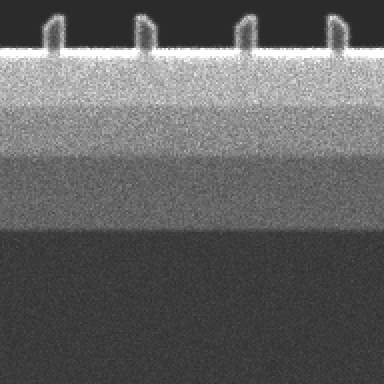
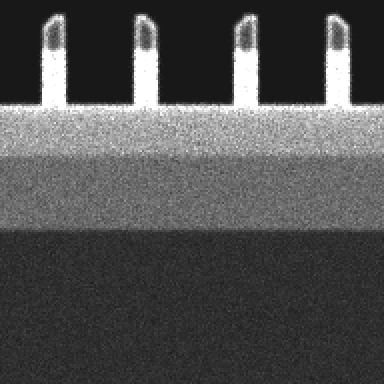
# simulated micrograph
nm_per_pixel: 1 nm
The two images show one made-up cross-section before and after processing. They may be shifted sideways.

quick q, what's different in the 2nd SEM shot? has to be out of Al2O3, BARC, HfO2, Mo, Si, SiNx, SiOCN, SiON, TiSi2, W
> HfO2 removed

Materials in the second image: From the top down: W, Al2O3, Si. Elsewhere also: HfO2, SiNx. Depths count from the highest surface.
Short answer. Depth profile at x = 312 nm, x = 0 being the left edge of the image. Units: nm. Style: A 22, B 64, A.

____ empty 90, W 50, Al2O3 74, Si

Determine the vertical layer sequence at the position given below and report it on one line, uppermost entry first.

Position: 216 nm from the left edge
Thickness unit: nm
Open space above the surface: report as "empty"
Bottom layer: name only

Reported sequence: empty 90, W 50, Al2O3 74, Si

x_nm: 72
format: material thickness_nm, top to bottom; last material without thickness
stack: empty 90, W 50, Al2O3 74, Si